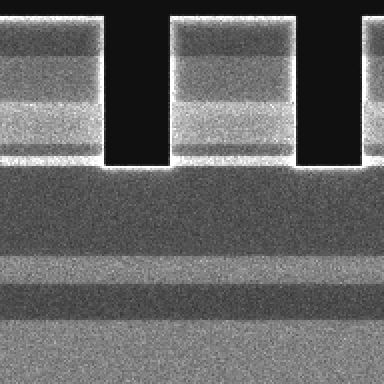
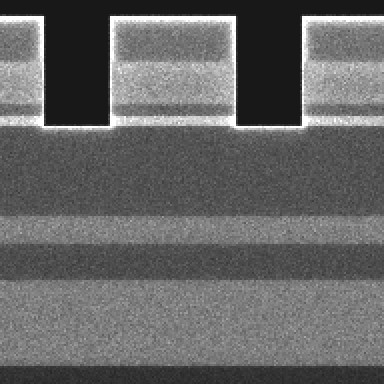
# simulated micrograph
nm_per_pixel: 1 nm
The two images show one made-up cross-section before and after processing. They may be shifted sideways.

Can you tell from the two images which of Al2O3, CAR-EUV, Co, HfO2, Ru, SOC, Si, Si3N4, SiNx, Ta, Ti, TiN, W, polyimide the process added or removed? Yes, it removed SOC.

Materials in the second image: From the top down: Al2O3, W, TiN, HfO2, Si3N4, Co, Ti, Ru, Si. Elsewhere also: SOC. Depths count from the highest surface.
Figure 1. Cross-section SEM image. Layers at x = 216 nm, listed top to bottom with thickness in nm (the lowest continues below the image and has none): Al2O3 46, W 42, TiN 12, HfO2 10, Si3N4 90, Co 28, Ti 36, Ru 86, Si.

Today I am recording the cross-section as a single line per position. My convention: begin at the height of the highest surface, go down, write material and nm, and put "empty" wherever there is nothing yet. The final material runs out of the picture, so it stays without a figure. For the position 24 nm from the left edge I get Al2O3 46, W 42, TiN 12, HfO2 10, Si3N4 90, Co 28, Ti 36, Ru 86, Si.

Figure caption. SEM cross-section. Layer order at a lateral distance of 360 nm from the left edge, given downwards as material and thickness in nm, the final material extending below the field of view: Al2O3 46, W 42, TiN 12, HfO2 10, Si3N4 90, Co 28, Ti 36, Ru 86, Si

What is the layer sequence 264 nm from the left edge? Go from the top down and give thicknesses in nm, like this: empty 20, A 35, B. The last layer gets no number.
empty 110, Si3N4 90, Co 28, Ti 36, Ru 86, Si